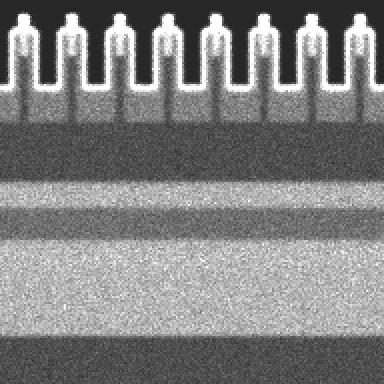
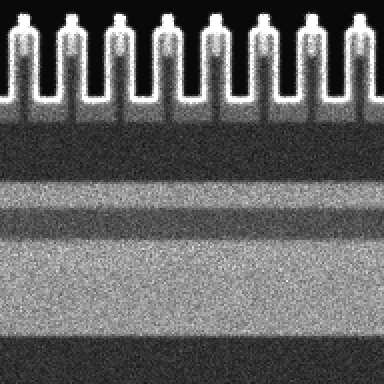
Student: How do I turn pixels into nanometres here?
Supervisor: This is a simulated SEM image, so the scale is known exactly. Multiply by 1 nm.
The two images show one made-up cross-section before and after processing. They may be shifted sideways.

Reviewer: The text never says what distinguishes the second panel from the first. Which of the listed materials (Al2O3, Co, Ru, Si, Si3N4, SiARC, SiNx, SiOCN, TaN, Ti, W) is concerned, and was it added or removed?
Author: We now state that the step removed Si3N4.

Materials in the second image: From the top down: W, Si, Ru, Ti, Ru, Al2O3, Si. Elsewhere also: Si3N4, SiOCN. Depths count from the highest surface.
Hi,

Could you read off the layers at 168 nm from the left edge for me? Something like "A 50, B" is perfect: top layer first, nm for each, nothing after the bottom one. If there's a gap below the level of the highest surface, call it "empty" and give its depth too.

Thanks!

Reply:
W 40, Si 126, Ru 26, Ti 32, Ru 28, Al2O3 68, Si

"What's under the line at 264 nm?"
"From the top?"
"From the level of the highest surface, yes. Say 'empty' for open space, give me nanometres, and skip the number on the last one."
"W 40, Si 126, Ru 26, Ti 32, Ru 28, Al2O3 68, Si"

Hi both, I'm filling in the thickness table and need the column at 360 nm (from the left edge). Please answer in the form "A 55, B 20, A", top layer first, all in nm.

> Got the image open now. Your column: W 40, Si 126, Ru 26, Ti 32, Ru 28, Al2O3 68, Si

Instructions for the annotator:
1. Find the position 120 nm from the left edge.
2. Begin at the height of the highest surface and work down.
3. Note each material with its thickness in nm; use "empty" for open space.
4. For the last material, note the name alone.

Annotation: W 40, Si 126, Ru 26, Ti 32, Ru 28, Al2O3 68, Si